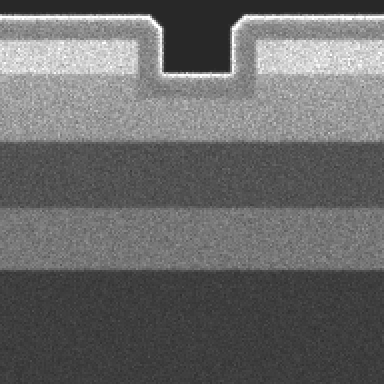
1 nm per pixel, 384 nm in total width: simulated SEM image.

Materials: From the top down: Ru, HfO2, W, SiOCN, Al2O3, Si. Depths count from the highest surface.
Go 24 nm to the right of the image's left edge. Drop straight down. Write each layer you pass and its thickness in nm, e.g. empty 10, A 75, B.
Ru 24, HfO2 34, W 68, SiOCN 66, Al2O3 62, Si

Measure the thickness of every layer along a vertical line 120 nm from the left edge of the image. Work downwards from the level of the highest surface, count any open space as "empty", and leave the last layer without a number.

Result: Ru 24, HfO2 34, W 68, SiOCN 66, Al2O3 62, Si